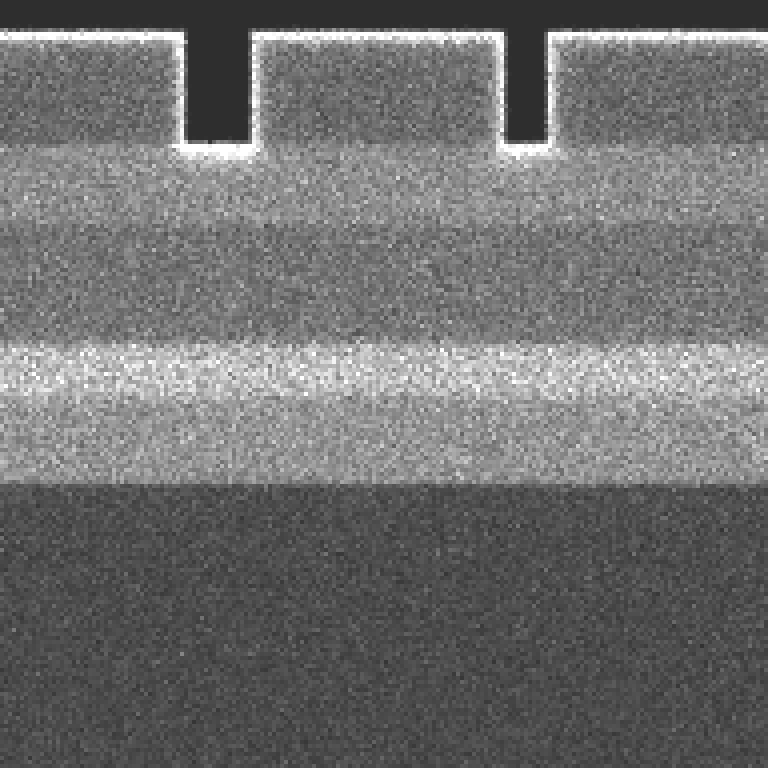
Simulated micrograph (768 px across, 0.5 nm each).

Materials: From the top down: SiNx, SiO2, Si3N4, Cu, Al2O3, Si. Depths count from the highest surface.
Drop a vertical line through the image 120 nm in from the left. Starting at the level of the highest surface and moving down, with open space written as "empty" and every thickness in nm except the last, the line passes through empty 56, SiO2 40, Si3N4 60, Cu 26, Al2O3 44, Si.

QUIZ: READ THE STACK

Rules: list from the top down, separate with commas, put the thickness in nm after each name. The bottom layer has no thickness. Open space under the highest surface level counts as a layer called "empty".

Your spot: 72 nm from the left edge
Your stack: SiNx 56, SiO2 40, Si3N4 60, Cu 26, Al2O3 44, Si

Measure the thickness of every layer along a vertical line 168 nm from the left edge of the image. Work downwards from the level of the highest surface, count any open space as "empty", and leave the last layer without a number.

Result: SiNx 56, SiO2 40, Si3N4 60, Cu 26, Al2O3 44, Si